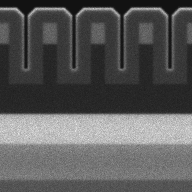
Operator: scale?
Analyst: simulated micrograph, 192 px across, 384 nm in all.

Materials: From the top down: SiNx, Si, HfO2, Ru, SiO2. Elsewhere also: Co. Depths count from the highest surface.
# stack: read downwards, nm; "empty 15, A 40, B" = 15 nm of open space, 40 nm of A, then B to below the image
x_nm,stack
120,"SiNx 152, Si 60, HfO2 60, Ru 72, SiO2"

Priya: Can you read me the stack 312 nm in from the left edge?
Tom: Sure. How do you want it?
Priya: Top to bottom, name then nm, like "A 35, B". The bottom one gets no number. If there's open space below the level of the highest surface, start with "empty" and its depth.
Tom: SiNx 152, Si 60, HfO2 60, Ru 72, SiO2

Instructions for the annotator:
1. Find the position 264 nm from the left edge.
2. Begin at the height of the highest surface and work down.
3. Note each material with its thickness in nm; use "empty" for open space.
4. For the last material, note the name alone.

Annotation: SiNx 152, Si 60, HfO2 60, Ru 72, SiO2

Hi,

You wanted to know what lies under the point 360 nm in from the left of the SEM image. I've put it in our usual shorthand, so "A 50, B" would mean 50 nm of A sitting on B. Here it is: SiNx 152, Si 60, HfO2 60, Ru 72, SiO2